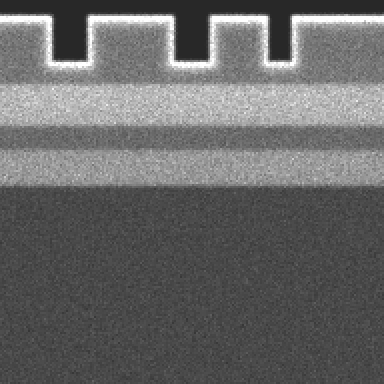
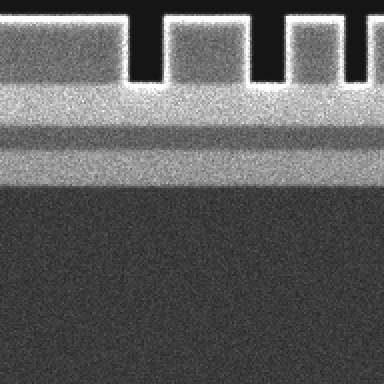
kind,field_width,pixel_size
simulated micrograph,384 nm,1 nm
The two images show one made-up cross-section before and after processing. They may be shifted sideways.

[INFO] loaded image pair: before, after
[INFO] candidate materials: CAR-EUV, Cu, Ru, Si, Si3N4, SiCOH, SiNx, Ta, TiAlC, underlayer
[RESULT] removed underlayer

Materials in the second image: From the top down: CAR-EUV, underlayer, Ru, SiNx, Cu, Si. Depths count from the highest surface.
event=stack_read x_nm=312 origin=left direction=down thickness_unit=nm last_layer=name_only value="CAR-EUV 46, underlayer 22, Ru 42, SiNx 24, Cu 36, Si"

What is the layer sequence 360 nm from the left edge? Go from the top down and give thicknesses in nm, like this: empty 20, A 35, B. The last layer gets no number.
empty 68, Ru 42, SiNx 24, Cu 36, Si